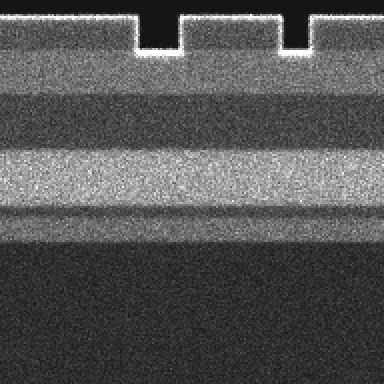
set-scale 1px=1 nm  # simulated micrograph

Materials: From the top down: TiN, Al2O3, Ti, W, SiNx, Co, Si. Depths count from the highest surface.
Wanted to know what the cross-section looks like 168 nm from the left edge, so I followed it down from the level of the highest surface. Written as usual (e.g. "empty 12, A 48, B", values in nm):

empty 34, Al2O3 44, Ti 56, W 56, SiNx 12, Co 24, Si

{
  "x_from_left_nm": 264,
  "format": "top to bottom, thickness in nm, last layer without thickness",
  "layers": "TiN 34, Al2O3 44, Ti 56, W 56, SiNx 12, Co 24, Si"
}